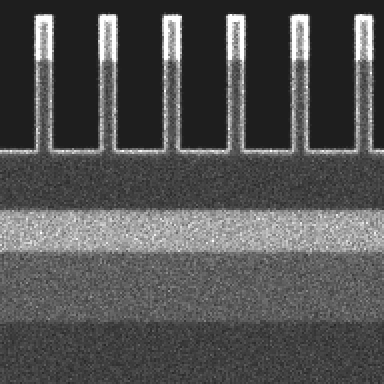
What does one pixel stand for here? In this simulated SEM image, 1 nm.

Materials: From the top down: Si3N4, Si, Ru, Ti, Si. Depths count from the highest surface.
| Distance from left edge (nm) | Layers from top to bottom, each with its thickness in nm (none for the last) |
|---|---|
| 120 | empty 134, Si 60, Ru 42, Ti 70, Si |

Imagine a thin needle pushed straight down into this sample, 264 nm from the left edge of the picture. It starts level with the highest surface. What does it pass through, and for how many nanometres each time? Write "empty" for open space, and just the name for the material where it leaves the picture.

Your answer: empty 134, Si 60, Ru 42, Ti 70, Si